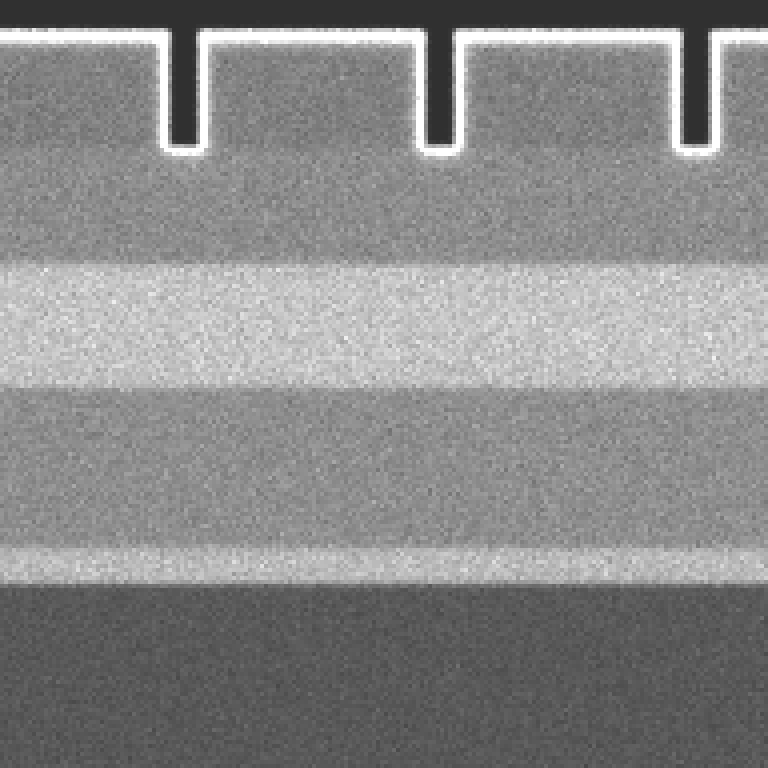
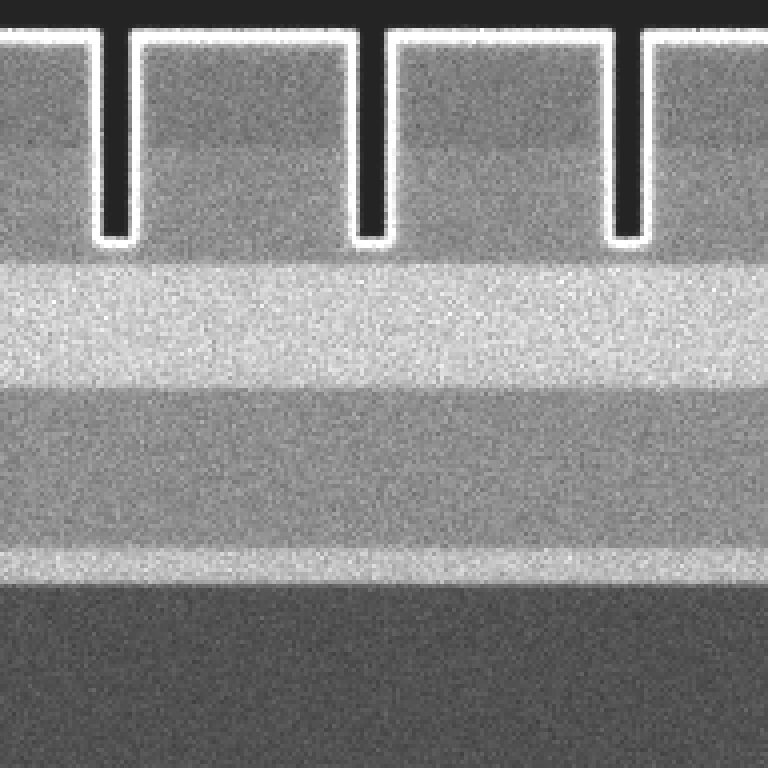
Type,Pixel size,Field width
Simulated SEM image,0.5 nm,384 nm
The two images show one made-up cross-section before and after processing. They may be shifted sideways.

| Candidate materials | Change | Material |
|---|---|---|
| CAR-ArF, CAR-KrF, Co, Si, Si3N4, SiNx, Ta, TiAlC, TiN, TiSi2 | removed | TiN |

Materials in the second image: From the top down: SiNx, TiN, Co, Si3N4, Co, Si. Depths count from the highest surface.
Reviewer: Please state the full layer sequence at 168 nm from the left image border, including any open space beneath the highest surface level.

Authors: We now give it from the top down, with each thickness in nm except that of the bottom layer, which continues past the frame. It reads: SiNx 58, TiN 58, Co 62, Si3N4 80, Co 18, Si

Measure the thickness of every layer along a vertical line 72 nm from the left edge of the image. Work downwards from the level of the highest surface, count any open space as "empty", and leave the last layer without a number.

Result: SiNx 58, TiN 58, Co 62, Si3N4 80, Co 18, Si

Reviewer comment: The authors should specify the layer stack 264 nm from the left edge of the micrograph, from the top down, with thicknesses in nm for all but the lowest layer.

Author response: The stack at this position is SiNx 58, TiN 58, Co 62, Si3N4 80, Co 18, Si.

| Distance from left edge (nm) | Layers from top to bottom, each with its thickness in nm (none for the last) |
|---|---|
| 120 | SiNx 58, TiN 58, Co 62, Si3N4 80, Co 18, Si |